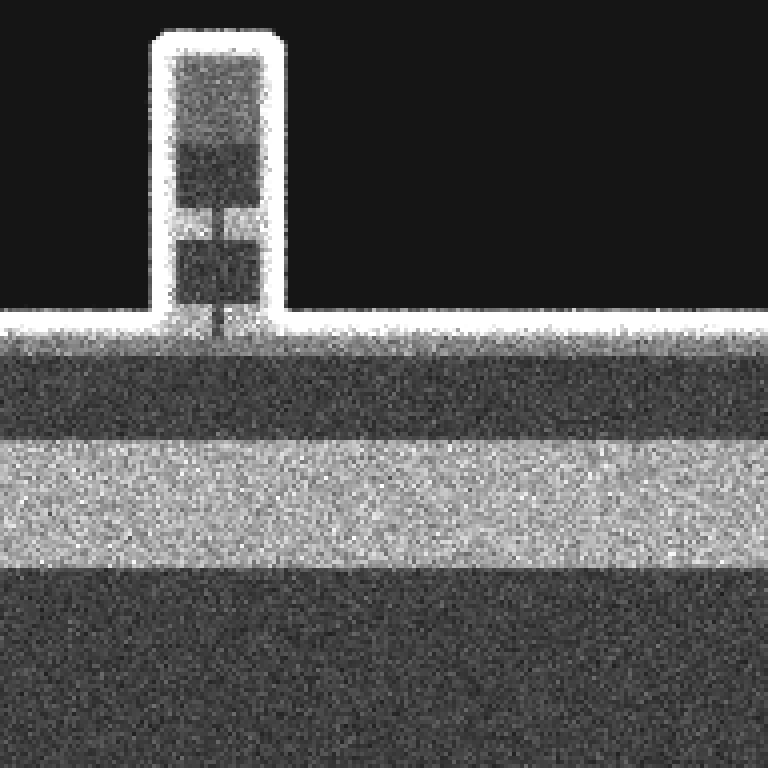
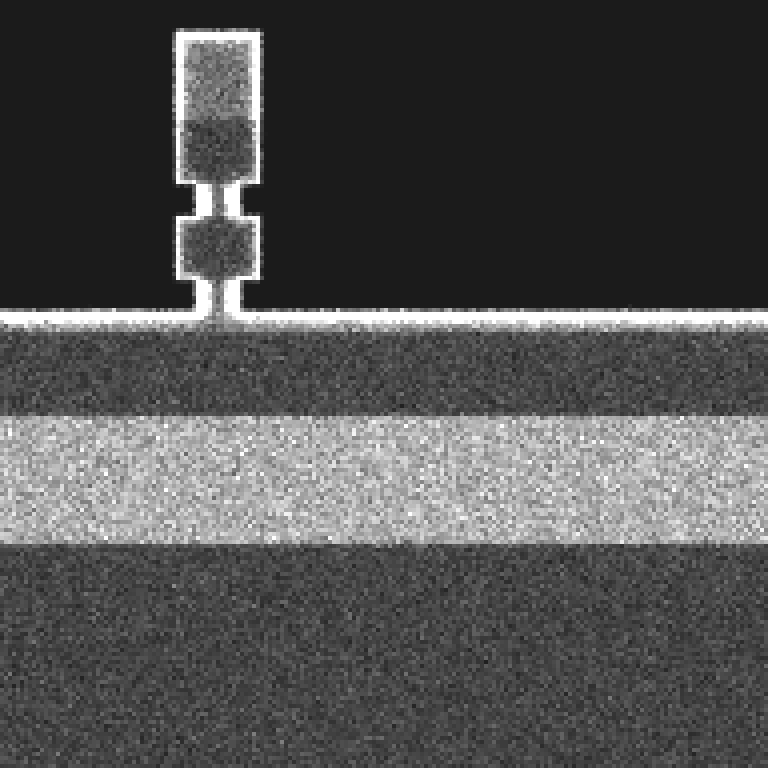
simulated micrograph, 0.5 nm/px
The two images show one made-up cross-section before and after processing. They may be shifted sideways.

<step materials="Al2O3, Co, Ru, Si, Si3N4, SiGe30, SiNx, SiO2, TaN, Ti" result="removed Al2O3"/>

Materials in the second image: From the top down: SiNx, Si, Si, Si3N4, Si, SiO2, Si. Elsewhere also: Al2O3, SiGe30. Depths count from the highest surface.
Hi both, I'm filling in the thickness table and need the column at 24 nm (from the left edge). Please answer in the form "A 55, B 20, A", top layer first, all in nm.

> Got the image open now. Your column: empty 140, Si3N4 10, Si 42, SiO2 64, Si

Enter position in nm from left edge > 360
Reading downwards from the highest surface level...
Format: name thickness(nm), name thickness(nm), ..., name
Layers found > empty 140, Si3N4 10, Si 42, SiO2 64, Si